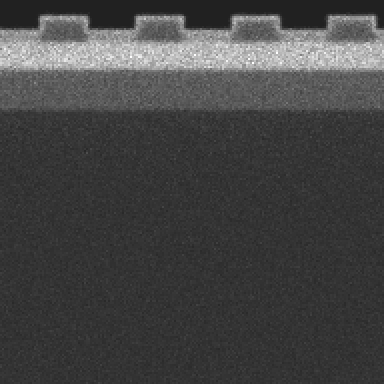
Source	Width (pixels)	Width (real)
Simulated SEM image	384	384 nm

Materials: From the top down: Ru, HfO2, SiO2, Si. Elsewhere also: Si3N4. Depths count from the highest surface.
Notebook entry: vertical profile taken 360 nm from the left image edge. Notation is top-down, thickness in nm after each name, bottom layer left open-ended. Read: Si3N4 26, HfO2 28, SiO2 40, Si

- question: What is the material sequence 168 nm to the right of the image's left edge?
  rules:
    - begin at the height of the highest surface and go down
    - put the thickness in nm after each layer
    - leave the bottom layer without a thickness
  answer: Si3N4 26, HfO2 28, SiO2 40, Si